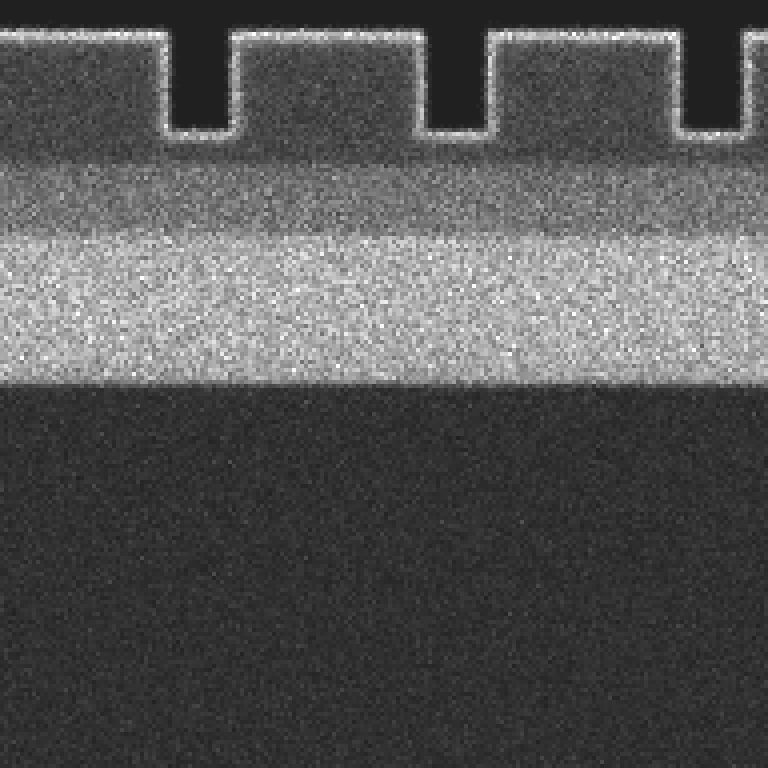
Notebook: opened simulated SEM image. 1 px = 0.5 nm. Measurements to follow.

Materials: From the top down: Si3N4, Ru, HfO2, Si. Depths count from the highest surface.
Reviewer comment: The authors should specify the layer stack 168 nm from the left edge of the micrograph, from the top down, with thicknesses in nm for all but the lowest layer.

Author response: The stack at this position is Si3N4 66, Ru 36, HfO2 74, Si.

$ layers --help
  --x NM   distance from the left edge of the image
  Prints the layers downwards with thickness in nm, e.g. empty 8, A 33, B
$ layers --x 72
Si3N4 66, Ru 36, HfO2 74, Si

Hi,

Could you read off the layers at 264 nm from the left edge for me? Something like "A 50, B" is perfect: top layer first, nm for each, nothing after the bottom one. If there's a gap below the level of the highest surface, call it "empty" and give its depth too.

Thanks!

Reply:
Si3N4 66, Ru 36, HfO2 74, Si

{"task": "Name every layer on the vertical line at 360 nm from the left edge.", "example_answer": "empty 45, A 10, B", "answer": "empty 50, Si3N4 16, Ru 36, HfO2 74, Si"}